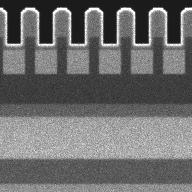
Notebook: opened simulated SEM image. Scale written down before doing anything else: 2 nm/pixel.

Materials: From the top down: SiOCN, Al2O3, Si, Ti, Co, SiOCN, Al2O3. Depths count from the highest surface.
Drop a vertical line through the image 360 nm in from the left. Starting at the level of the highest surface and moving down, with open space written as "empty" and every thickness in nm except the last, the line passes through empty 72, SiOCN 12, Al2O3 48, Si 60, Ti 26, Co 84, SiOCN 50, Al2O3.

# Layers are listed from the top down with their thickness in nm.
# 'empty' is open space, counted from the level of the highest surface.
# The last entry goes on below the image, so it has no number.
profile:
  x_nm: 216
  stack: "empty 72, SiOCN 12, Al2O3 48, Si 60, Ti 26, Co 84, SiOCN 50, Al2O3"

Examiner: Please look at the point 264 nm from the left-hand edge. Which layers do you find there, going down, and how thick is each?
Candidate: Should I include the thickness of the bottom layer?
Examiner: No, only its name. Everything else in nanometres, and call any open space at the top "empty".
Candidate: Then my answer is empty 4, SiOCN 80, Al2O3 48, Si 60, Ti 26, Co 84, SiOCN 50, Al2O3